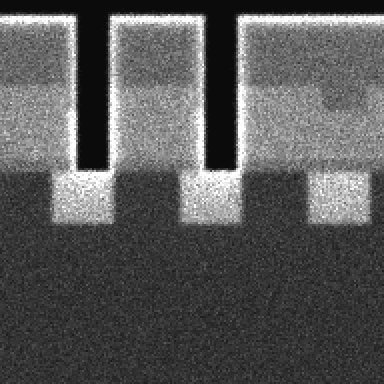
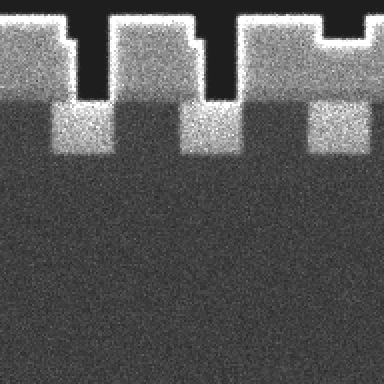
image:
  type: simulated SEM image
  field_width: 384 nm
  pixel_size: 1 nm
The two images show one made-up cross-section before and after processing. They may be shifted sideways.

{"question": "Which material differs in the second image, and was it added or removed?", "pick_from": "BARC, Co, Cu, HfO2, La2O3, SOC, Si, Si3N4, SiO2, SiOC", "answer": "SOC, removed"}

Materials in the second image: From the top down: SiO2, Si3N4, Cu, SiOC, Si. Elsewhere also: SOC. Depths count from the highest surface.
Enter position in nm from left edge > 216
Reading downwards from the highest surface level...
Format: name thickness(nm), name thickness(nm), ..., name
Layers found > empty 86, Cu 52, SiOC 28, Si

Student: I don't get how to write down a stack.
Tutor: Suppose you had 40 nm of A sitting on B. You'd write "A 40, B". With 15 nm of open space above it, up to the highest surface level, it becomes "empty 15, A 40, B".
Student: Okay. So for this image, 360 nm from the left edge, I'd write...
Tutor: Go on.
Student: empty 24, SiO2 50, Si3N4 12, Cu 52, SiOC 28, Si